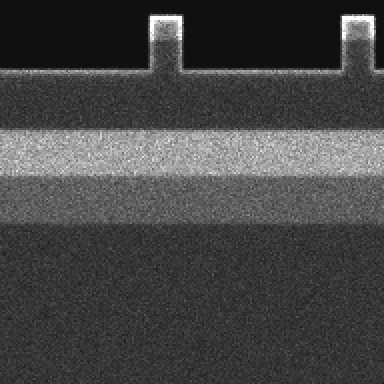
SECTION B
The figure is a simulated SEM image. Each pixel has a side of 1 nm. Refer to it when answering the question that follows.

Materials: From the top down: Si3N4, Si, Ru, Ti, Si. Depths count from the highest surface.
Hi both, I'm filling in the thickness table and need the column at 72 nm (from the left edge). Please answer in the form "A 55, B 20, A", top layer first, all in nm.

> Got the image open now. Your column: empty 54, Si 60, Ru 46, Ti 48, Si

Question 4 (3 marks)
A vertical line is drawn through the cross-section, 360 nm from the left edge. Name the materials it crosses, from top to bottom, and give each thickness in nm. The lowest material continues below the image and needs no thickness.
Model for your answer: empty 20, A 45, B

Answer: Si3N4 24, Si 90, Ru 46, Ti 48, Si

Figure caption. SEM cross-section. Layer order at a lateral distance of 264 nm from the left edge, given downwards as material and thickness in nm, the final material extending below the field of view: empty 54, Si 60, Ru 46, Ti 48, Si